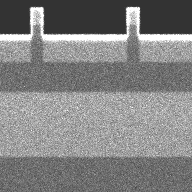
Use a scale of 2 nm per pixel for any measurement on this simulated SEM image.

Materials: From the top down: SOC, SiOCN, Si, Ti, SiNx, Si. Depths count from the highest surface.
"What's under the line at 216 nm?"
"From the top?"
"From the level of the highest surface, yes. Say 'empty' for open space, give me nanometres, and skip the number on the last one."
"empty 54, SOC 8, SiOCN 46, Si 60, Ti 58, SiNx 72, Si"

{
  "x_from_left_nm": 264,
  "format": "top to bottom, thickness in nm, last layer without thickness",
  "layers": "Ti 34, Si 134, Ti 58, SiNx 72, Si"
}